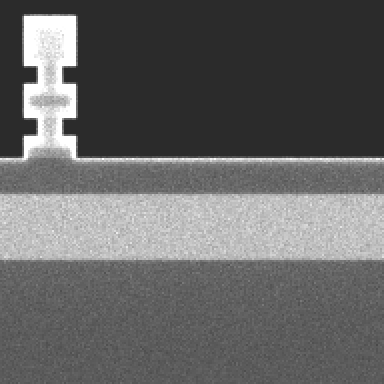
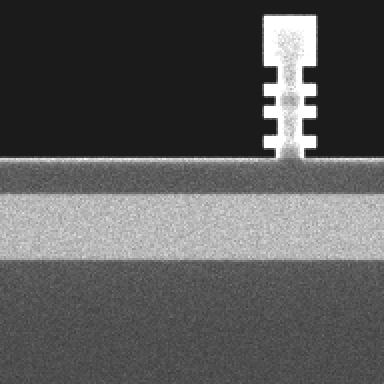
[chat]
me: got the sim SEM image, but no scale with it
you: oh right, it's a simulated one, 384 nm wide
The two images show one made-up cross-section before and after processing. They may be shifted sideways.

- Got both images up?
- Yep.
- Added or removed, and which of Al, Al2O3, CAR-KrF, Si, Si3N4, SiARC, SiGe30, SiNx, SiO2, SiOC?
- removed, SiNx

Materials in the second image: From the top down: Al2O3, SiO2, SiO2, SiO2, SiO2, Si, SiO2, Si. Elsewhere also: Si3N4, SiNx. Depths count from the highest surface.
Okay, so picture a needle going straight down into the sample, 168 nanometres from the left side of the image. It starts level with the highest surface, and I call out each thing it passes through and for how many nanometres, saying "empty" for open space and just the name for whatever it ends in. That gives empty 142, Si 36, SiO2 66, Si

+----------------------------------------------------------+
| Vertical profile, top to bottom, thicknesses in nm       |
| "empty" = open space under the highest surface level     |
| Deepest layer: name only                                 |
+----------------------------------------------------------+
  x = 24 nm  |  empty 142, Si 36, SiO2 66, Si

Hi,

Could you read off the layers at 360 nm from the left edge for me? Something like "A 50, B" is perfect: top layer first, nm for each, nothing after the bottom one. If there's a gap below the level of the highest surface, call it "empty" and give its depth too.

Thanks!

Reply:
empty 142, Si 36, SiO2 66, Si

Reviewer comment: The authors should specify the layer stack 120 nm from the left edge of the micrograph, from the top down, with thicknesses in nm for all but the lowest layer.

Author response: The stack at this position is empty 142, Si 36, SiO2 66, Si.